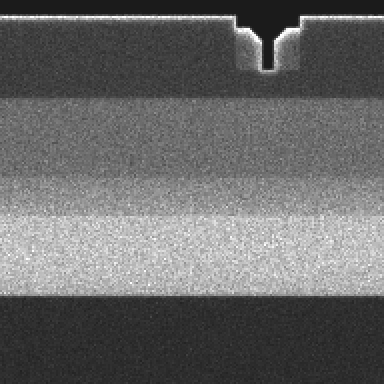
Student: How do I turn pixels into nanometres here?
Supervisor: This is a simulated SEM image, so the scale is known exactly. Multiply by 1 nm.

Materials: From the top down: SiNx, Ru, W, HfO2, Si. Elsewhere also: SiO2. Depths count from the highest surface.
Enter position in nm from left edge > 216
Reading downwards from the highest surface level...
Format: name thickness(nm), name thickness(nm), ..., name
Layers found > SiNx 82, Ru 80, W 38, HfO2 80, Si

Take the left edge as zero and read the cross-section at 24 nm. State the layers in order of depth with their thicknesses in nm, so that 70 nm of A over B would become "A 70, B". SiNx 82, Ru 80, W 38, HfO2 80, Si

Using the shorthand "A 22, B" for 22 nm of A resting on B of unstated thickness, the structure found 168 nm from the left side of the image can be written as SiNx 82, Ru 80, W 38, HfO2 80, Si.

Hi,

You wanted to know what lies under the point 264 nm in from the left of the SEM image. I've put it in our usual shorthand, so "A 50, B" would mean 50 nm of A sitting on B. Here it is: empty 54, SiNx 28, Ru 80, W 38, HfO2 80, Si